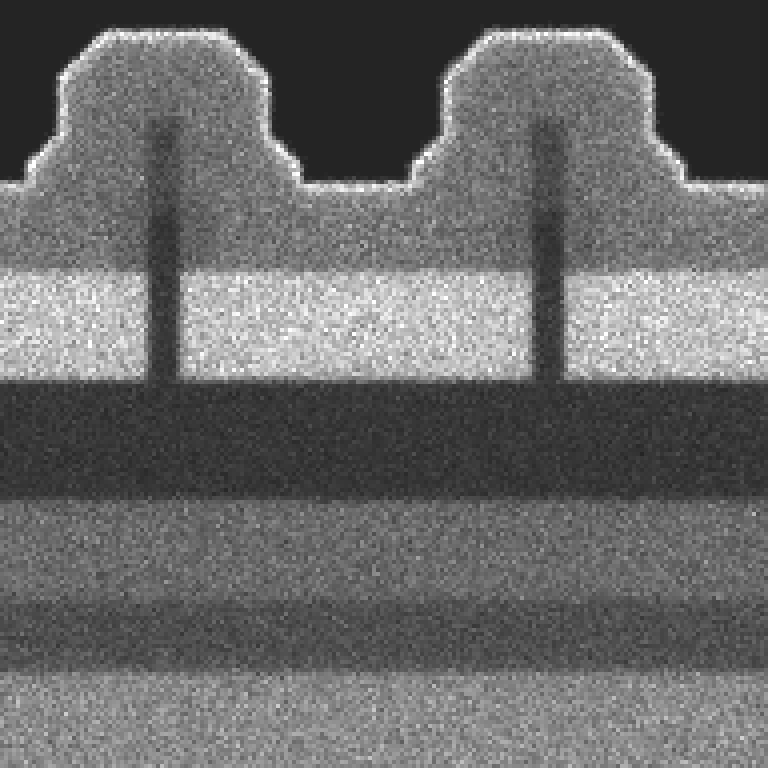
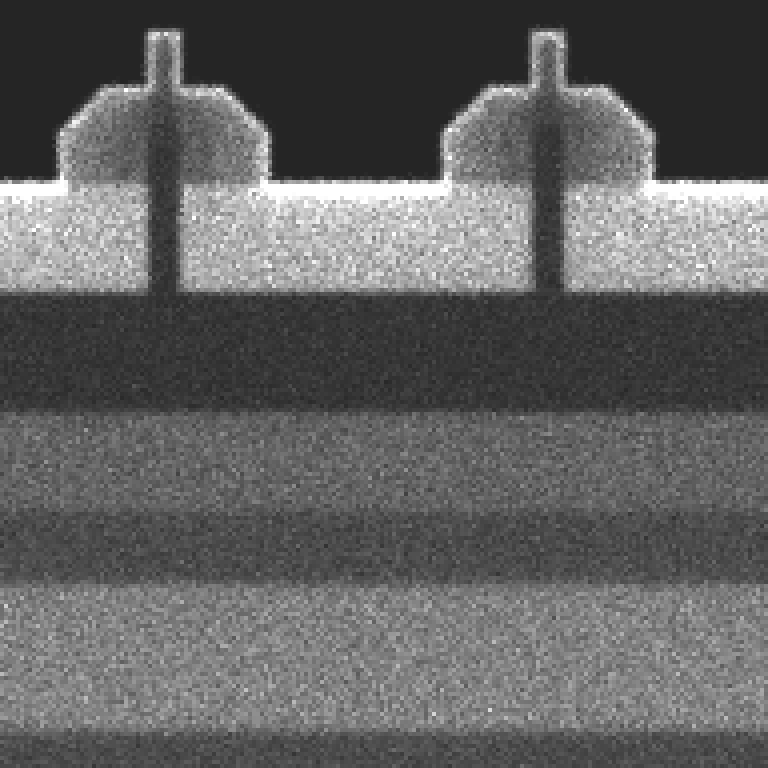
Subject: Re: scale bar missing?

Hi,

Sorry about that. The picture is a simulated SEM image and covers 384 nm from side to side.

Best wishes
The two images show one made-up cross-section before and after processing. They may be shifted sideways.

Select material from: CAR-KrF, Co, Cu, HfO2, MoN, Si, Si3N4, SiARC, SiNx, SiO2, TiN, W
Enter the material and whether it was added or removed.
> Co / removed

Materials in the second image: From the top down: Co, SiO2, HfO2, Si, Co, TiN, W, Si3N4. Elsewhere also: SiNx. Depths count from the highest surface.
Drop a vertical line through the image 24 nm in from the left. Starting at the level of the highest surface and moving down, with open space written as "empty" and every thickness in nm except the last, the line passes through empty 76, HfO2 54, Si 60, Co 50, TiN 36, W 74, Si3N4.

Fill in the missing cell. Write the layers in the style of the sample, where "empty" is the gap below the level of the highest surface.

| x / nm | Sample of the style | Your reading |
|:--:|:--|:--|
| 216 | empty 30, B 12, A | empty 76, HfO2 54, Si 60, Co 50, TiN 36, W 74, Si3N4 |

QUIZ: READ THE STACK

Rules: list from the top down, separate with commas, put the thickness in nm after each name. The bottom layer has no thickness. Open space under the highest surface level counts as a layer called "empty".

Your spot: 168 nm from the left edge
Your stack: empty 76, HfO2 54, Si 60, Co 50, TiN 36, W 74, Si3N4